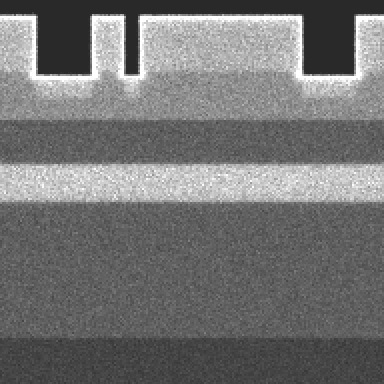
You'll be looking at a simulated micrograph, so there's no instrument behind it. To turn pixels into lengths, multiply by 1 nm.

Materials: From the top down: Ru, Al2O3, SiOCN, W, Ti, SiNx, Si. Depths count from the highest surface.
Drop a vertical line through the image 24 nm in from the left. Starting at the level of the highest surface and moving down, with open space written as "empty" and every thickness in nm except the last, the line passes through Ru 56, Al2O3 48, SiOCN 44, W 38, Ti 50, SiNx 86, Si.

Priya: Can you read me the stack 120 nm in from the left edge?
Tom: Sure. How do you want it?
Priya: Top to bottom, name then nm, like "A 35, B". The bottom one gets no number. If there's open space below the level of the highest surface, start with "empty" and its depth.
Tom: Ru 56, Al2O3 48, SiOCN 44, W 38, Ti 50, SiNx 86, Si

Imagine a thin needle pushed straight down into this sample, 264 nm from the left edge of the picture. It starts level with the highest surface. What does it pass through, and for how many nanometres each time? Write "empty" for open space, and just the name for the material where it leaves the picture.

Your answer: Ru 56, Al2O3 48, SiOCN 44, W 38, Ti 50, SiNx 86, Si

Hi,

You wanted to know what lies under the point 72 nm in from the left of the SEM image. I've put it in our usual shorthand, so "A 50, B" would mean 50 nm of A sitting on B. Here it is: empty 60, Ru 22, Al2O3 22, SiOCN 44, W 38, Ti 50, SiNx 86, Si